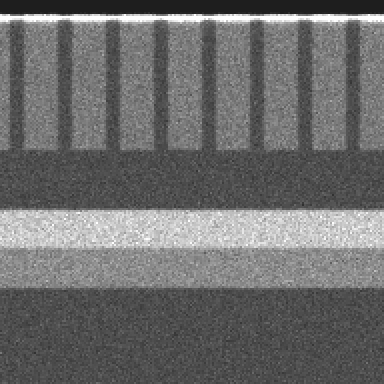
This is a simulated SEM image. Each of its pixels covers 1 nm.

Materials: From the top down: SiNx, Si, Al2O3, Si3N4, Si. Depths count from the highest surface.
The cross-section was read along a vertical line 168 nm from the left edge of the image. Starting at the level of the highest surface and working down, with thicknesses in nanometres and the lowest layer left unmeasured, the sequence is SiNx 134, Si 60, Al2O3 38, Si3N4 40, Si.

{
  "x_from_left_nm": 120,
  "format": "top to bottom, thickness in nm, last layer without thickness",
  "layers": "SiNx 134, Si 60, Al2O3 38, Si3N4 40, Si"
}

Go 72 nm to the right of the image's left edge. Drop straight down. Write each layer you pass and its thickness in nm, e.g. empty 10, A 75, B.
SiNx 134, Si 60, Al2O3 38, Si3N4 40, Si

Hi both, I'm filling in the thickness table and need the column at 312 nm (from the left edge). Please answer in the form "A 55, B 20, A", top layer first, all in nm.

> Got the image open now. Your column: SiNx 134, Si 60, Al2O3 38, Si3N4 40, Si